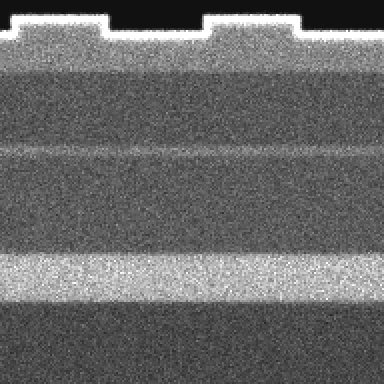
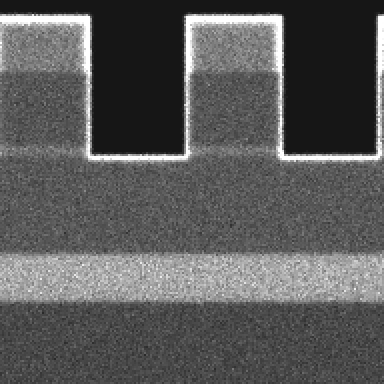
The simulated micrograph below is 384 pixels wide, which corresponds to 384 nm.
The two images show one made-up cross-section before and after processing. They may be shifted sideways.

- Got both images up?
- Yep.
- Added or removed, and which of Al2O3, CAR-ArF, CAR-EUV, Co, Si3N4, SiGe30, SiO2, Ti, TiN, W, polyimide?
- removed, Al2O3 and Co and TiN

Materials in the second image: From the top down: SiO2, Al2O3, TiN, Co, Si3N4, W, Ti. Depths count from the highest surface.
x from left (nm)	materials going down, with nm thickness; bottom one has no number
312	empty 140, Si3N4 98, W 48, Ti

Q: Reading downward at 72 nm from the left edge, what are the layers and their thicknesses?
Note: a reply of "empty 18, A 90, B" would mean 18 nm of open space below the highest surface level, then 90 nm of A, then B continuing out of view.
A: SiO2 16, Al2O3 40, TiN 74, Co 10, Si3N4 98, W 48, Ti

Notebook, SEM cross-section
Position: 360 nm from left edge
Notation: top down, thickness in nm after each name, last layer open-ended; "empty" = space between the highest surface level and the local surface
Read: empty 140, Si3N4 98, W 48, Ti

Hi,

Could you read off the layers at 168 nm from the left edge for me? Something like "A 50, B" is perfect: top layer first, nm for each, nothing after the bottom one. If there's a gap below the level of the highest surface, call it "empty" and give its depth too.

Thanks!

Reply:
empty 140, Si3N4 98, W 48, Ti